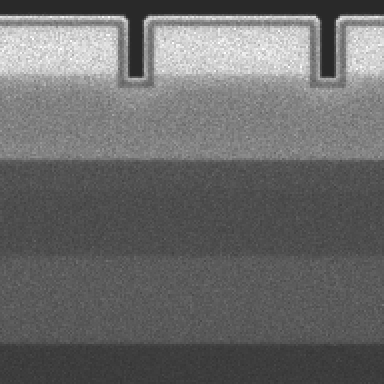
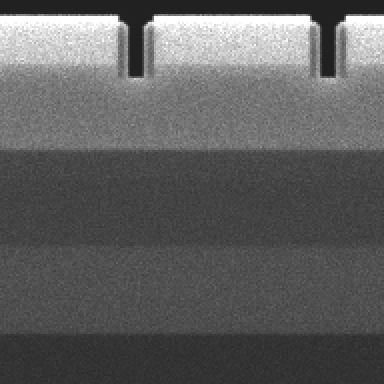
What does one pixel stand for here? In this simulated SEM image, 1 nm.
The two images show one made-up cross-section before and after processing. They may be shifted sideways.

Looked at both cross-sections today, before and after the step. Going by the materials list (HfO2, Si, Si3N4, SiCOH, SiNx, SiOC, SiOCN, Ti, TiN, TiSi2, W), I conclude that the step removed Si3N4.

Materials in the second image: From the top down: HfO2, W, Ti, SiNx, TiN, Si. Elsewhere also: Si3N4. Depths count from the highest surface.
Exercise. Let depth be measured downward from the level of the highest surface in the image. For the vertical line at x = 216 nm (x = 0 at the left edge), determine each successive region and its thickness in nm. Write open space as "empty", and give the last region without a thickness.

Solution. HfO2 48, W 86, Ti 30, SiNx 66, TiN 88, Si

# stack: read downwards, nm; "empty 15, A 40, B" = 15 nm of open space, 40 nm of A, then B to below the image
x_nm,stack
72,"HfO2 48, W 86, Ti 30, SiNx 66, TiN 88, Si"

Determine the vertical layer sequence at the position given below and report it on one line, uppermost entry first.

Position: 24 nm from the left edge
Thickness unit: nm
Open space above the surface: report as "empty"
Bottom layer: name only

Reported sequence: HfO2 48, W 86, Ti 30, SiNx 66, TiN 88, Si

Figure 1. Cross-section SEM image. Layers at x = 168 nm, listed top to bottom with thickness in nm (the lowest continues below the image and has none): HfO2 48, W 86, Ti 30, SiNx 66, TiN 88, Si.